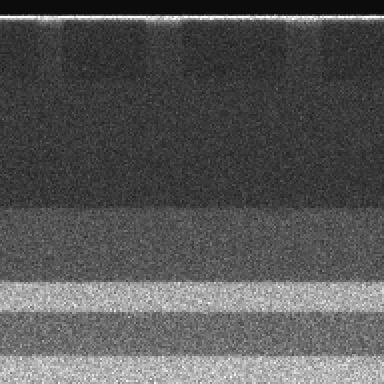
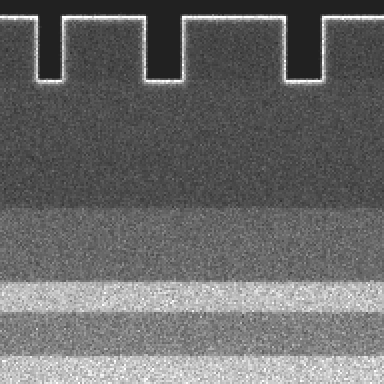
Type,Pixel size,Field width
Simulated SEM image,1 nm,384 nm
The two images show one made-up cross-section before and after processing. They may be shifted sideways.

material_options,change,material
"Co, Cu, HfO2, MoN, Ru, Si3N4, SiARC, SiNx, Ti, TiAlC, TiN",removed,SiARC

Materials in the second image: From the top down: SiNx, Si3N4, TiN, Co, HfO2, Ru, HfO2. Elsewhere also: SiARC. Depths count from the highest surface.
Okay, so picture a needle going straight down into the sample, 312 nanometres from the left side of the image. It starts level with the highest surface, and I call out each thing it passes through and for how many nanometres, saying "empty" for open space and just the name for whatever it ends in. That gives empty 64, Si3N4 70, TiN 58, Co 74, HfO2 30, Ru 44, HfO2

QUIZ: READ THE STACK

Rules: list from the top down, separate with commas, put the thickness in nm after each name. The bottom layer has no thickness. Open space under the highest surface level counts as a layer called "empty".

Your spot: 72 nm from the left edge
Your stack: SiNx 64, Si3N4 70, TiN 58, Co 74, HfO2 30, Ru 44, HfO2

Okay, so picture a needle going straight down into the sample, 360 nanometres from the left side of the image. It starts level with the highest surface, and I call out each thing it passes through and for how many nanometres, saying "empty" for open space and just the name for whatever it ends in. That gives SiNx 64, Si3N4 70, TiN 58, Co 74, HfO2 30, Ru 44, HfO2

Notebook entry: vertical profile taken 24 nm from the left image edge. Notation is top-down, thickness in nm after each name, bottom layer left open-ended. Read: SiNx 64, Si3N4 70, TiN 58, Co 74, HfO2 30, Ru 44, HfO2